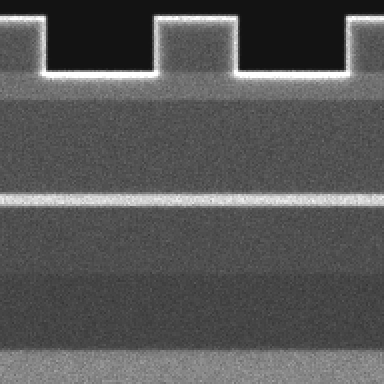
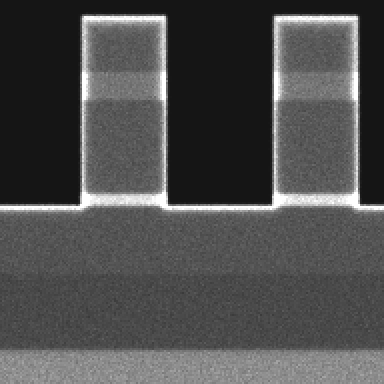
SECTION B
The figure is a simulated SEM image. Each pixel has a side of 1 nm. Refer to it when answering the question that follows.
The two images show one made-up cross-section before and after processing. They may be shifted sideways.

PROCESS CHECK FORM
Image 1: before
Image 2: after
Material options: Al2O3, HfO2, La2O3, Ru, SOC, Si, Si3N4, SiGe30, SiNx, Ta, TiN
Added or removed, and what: removed, Al2O3 and HfO2 and TiN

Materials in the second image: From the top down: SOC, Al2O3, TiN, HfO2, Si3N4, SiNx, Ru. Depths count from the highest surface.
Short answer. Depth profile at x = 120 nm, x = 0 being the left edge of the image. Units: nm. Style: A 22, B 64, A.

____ SOC 56, Al2O3 28, TiN 94, HfO2 12, Si3N4 68, SiNx 76, Ru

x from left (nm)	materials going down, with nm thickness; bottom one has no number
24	empty 190, Si3N4 68, SiNx 76, Ru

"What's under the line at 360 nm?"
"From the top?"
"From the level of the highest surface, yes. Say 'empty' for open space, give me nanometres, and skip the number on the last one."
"empty 190, Si3N4 68, SiNx 76, Ru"